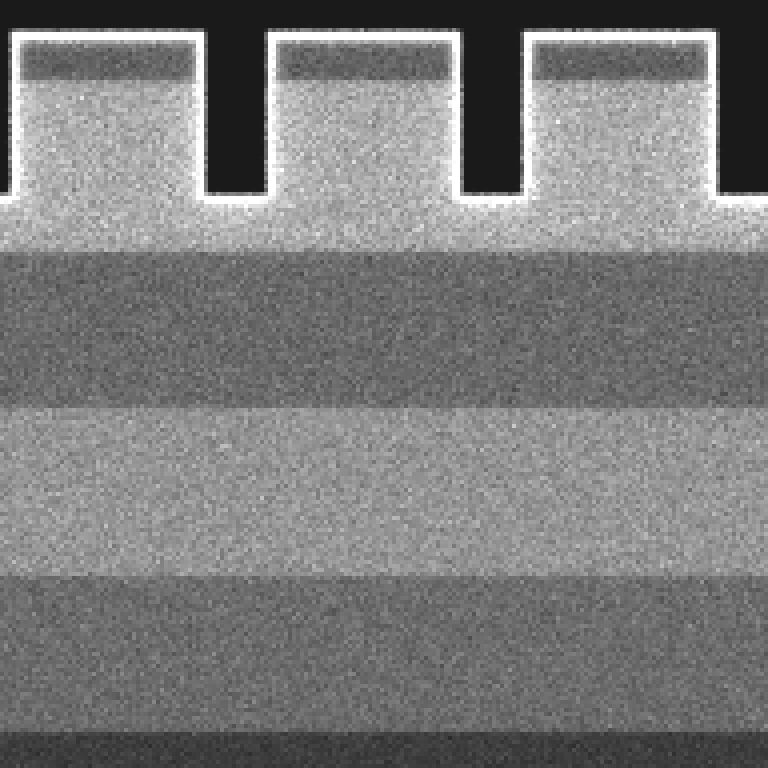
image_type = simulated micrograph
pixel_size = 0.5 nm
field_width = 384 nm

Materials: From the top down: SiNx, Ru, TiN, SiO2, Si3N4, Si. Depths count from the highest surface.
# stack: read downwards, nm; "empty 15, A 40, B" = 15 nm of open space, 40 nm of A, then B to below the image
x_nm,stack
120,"empty 82, Ru 28, TiN 78, SiO2 84, Si3N4 78, Si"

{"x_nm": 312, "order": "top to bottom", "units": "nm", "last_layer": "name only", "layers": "SiNx 24, Ru 86, TiN 78, SiO2 84, Si3N4 78, Si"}